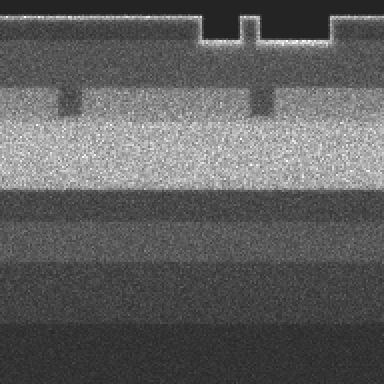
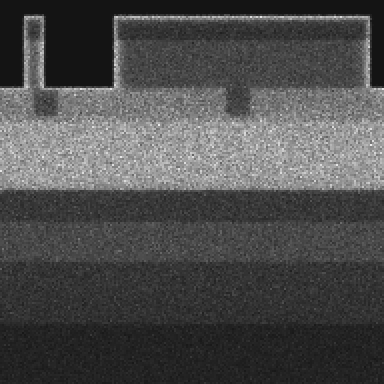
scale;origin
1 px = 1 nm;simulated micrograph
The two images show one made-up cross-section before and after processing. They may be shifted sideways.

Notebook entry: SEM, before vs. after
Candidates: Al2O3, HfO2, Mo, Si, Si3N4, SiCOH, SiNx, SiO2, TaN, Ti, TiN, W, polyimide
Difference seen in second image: SiO2 removed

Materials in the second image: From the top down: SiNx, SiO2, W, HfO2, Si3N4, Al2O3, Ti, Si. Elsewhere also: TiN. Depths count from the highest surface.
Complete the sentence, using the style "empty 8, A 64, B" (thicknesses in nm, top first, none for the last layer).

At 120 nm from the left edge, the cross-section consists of SiNx 24, SiO2 48, W 34, HfO2 68, Si3N4 32, Al2O3 40, Ti 62, Si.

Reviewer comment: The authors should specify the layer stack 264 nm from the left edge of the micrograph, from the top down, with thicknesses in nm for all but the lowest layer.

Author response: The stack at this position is SiNx 24, SiO2 48, W 34, HfO2 68, Si3N4 32, Al2O3 40, Ti 62, Si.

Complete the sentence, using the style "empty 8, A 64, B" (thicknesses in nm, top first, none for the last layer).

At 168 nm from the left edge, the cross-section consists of SiNx 24, SiO2 48, W 34, HfO2 68, Si3N4 32, Al2O3 40, Ti 62, Si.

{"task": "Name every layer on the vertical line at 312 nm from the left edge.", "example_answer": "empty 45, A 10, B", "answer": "SiNx 24, SiO2 48, W 34, HfO2 68, Si3N4 32, Al2O3 40, Ti 62, Si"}